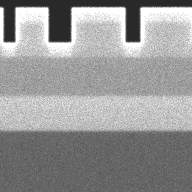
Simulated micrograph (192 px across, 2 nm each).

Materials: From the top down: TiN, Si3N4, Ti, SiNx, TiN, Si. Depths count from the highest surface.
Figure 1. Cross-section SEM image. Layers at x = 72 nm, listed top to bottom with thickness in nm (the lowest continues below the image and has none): TiN 28, Si3N4 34, Ti 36, SiNx 78, TiN 70, Si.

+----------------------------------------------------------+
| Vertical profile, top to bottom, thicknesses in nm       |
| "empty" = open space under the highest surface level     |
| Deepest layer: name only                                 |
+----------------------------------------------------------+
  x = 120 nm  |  empty 70, TiN 28, SiNx 78, TiN 70, Si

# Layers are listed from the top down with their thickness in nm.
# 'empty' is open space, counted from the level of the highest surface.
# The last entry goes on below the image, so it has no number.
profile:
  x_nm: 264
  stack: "empty 70, TiN 28, SiNx 78, TiN 70, Si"